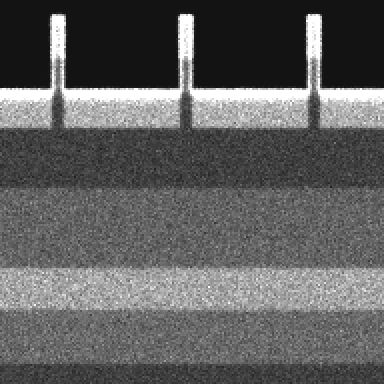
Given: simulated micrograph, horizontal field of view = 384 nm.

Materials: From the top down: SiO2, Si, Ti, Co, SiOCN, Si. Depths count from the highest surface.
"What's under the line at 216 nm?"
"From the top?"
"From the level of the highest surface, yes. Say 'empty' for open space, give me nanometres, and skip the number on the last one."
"empty 74, SiO2 38, Si 60, Ti 80, Co 42, SiOCN 54, Si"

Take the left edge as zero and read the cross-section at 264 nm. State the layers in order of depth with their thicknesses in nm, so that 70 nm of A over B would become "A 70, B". empty 74, SiO2 38, Si 60, Ti 80, Co 42, SiOCN 54, Si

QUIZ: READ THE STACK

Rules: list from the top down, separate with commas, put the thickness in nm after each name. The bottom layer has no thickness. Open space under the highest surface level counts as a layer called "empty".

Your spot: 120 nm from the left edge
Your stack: empty 74, SiO2 38, Si 60, Ti 80, Co 42, SiOCN 54, Si